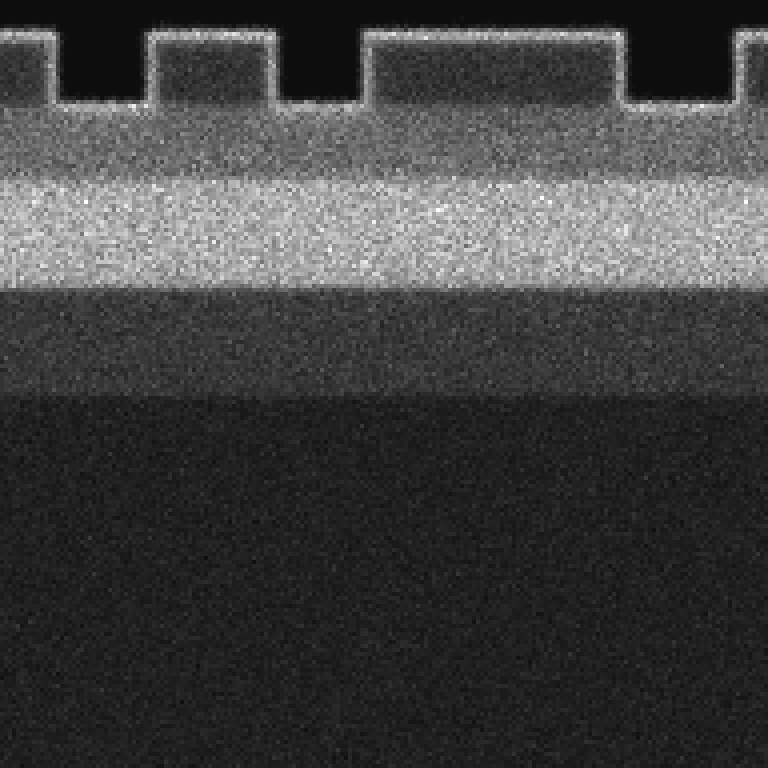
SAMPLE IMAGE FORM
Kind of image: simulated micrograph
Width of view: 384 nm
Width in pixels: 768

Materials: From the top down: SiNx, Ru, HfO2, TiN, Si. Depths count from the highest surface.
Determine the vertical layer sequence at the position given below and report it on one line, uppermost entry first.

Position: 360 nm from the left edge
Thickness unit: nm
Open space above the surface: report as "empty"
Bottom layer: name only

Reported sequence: empty 36, Ru 38, HfO2 54, TiN 54, Si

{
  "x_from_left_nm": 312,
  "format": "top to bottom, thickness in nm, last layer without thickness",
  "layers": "empty 36, Ru 38, HfO2 54, TiN 54, Si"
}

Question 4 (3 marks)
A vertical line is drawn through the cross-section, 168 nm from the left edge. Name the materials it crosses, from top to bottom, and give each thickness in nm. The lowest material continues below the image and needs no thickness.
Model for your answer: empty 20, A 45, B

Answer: empty 36, Ru 38, HfO2 54, TiN 54, Si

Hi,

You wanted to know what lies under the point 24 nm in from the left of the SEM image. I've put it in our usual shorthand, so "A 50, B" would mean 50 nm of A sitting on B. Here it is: SiNx 36, Ru 38, HfO2 54, TiN 54, Si